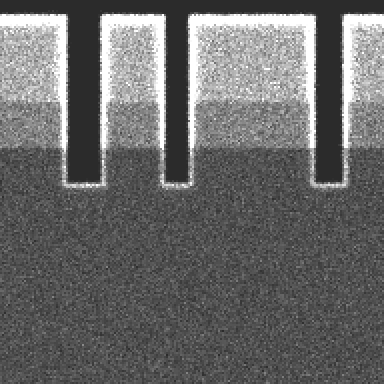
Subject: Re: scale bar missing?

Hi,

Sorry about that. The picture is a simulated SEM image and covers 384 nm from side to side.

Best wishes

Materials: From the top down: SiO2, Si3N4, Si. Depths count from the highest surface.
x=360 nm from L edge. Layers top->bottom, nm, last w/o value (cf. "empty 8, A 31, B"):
SiO2 86, Si3N4 46, Si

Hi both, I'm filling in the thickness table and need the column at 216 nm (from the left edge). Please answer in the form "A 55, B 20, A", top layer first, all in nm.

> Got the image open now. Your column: SiO2 86, Si3N4 46, Si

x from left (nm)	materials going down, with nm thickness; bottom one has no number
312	SiO2 86, Si3N4 46, Si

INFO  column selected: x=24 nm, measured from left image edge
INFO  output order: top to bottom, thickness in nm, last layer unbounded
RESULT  SiO2 86, Si3N4 46, Si